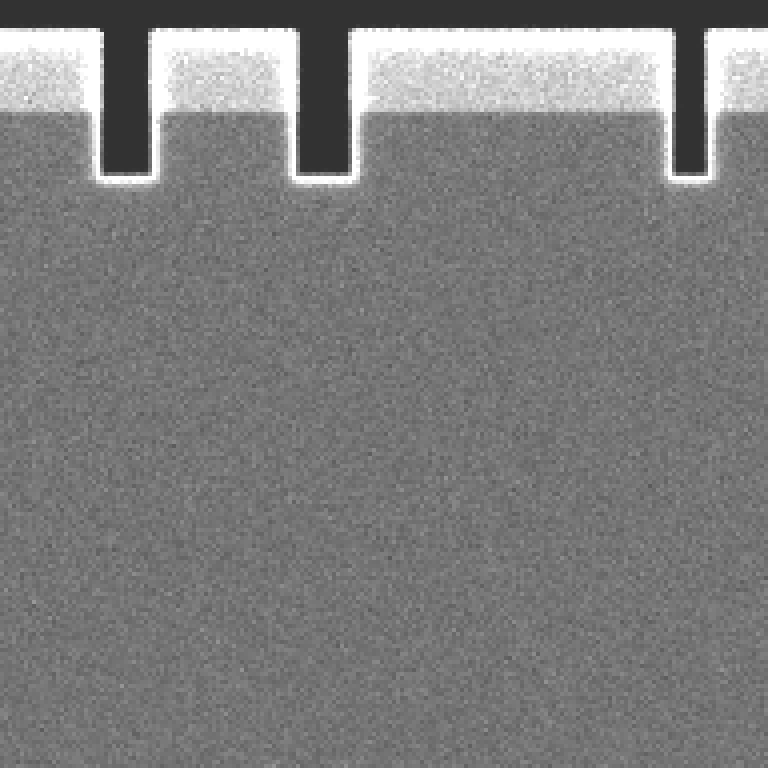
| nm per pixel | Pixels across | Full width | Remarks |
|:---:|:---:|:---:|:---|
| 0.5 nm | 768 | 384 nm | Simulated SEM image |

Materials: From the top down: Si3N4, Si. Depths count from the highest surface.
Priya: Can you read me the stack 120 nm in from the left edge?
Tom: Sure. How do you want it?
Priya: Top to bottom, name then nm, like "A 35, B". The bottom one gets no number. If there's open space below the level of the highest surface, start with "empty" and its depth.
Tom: Si3N4 40, Si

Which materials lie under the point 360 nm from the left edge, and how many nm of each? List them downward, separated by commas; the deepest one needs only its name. Si3N4 40, Si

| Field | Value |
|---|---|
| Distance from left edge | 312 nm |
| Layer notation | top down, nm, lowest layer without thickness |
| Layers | Si3N4 40, Si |